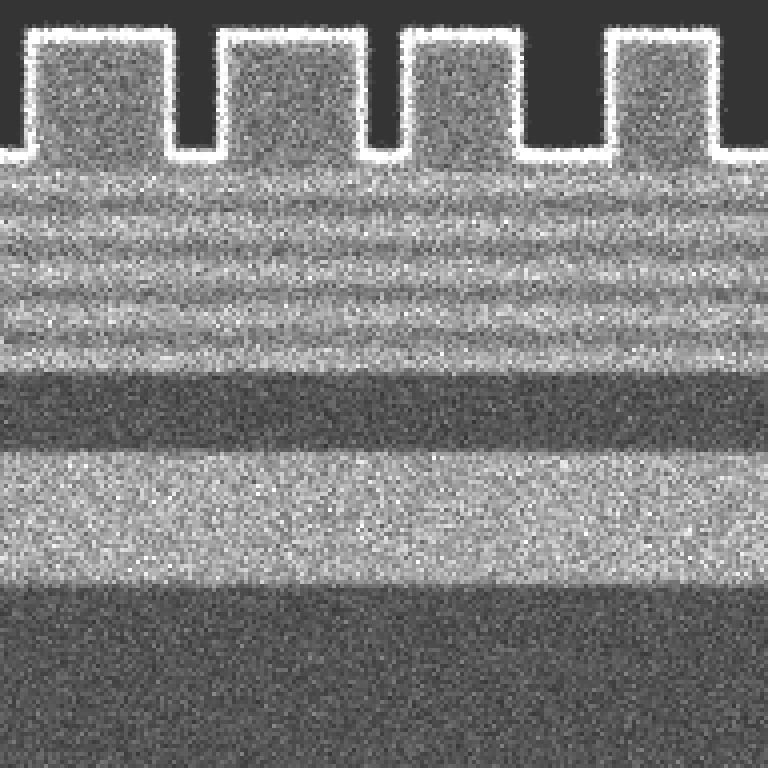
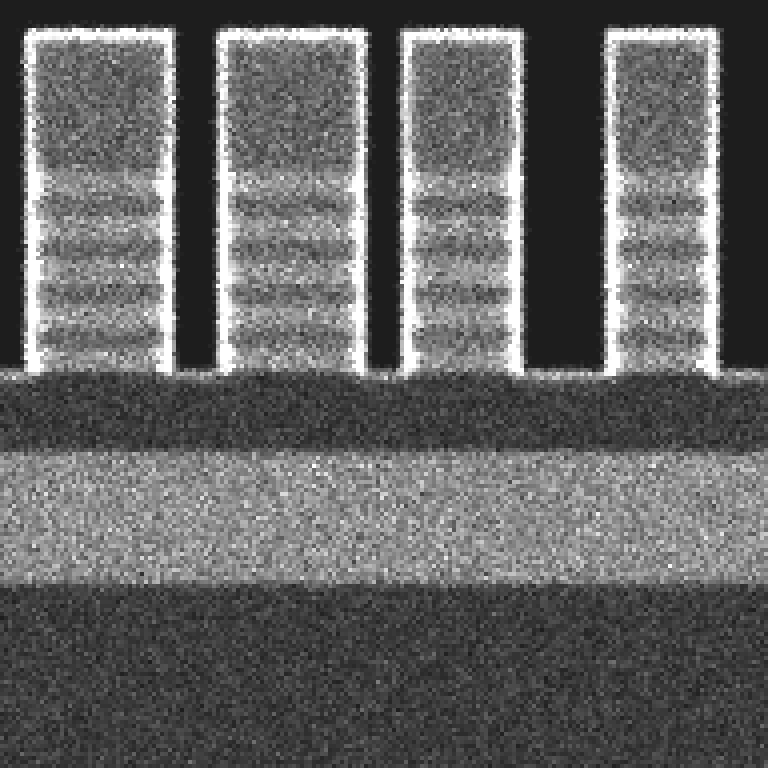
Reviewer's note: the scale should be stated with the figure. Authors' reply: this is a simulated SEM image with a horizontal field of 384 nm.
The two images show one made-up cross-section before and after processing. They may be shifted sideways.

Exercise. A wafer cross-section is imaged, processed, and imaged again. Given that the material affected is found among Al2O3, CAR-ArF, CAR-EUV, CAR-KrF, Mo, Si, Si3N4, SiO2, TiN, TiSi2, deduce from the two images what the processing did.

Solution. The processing removed Al2O3 and Si3N4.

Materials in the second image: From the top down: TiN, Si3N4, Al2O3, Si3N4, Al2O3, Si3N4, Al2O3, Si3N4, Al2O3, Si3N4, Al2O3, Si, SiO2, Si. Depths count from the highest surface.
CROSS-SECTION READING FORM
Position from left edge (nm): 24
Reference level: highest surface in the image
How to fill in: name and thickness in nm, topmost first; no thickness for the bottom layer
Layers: TiN 60, Si3N4 10, Al2O3 12, Si3N4 10, Al2O3 12, Si3N4 10, Al2O3 12, Si3N4 10, Al2O3 12, Si3N4 10, Al2O3 12, Si 40, SiO2 66, Si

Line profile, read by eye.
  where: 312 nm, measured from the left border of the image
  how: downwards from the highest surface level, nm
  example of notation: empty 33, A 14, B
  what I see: TiN 60, Si3N4 10, Al2O3 12, Si3N4 10, Al2O3 12, Si3N4 10, Al2O3 12, Si3N4 10, Al2O3 12, Si3N4 10, Al2O3 12, Si 40, SiO2 66, Si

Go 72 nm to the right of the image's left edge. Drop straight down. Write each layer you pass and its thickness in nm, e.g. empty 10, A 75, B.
TiN 60, Si3N4 10, Al2O3 12, Si3N4 10, Al2O3 12, Si3N4 10, Al2O3 12, Si3N4 10, Al2O3 12, Si3N4 10, Al2O3 12, Si 40, SiO2 66, Si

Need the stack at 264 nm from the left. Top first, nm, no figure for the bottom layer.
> empty 170, Si 40, SiO2 66, Si